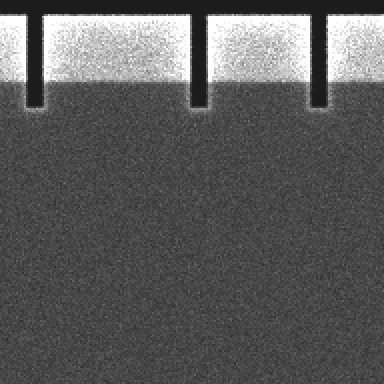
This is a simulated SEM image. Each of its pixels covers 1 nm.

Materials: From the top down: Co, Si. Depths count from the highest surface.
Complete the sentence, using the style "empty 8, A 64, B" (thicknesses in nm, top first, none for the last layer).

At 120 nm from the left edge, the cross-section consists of Co 66, Si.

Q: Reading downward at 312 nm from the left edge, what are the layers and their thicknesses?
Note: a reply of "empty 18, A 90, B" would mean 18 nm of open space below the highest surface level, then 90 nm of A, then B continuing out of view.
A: empty 92, Si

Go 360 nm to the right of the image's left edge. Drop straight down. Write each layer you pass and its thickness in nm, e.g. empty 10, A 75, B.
Co 66, Si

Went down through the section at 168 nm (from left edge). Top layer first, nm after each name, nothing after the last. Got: Co 66, Si